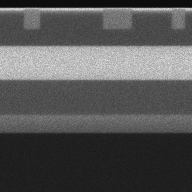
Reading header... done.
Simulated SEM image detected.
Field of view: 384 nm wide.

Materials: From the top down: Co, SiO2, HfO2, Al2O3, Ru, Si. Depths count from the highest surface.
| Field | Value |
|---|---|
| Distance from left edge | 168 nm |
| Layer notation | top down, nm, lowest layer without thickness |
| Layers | SiO2 76, HfO2 68, Al2O3 70, Ru 36, Si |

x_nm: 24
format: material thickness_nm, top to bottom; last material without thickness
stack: SiO2 76, HfO2 68, Al2O3 70, Ru 36, Si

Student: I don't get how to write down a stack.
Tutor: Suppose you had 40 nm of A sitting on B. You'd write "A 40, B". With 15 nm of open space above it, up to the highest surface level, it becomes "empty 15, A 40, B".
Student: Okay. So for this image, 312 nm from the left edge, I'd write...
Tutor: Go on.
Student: SiO2 76, HfO2 68, Al2O3 70, Ru 36, Si